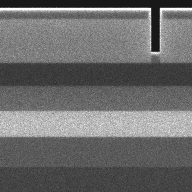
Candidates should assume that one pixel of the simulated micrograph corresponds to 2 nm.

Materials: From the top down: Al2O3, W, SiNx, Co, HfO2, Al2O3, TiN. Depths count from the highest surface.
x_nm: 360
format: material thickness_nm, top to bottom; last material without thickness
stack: Al2O3 22, W 88, SiNx 46, Co 50, HfO2 52, Al2O3 60, TiN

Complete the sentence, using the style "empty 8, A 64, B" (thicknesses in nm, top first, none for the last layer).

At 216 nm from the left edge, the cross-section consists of Al2O3 22, W 88, SiNx 46, Co 50, HfO2 52, Al2O3 60, TiN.